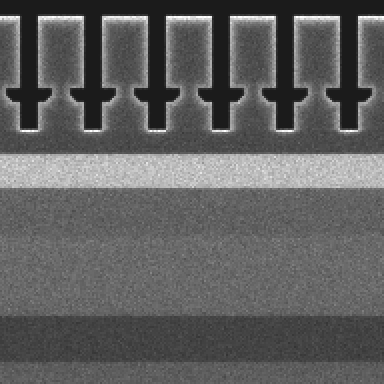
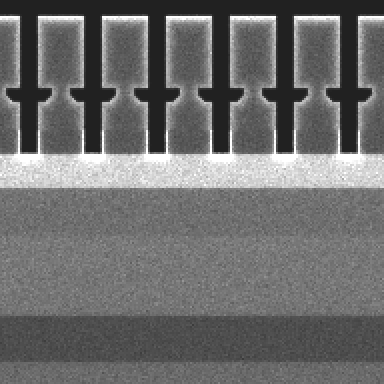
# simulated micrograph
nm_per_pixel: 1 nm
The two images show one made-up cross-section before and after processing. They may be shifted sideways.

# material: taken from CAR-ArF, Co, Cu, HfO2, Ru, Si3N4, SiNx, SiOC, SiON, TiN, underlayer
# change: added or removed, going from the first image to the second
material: TiN
change: removed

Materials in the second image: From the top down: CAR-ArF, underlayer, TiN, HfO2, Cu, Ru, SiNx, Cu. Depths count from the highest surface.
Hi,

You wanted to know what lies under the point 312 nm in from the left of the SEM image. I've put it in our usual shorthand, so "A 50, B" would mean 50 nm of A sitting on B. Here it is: CAR-ArF 72, underlayer 42, TiN 24, HfO2 34, Cu 48, Ru 80, SiNx 46, Cu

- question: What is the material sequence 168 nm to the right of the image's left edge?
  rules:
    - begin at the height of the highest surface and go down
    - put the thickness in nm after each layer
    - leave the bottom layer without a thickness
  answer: CAR-ArF 72, empty 14, underlayer 28, TiN 24, HfO2 34, Cu 48, Ru 80, SiNx 46, Cu